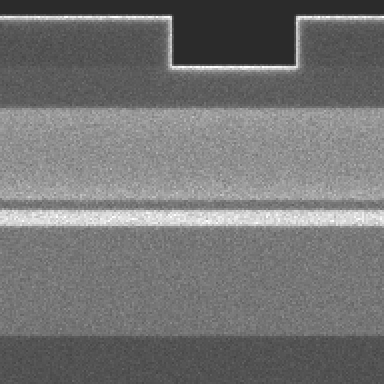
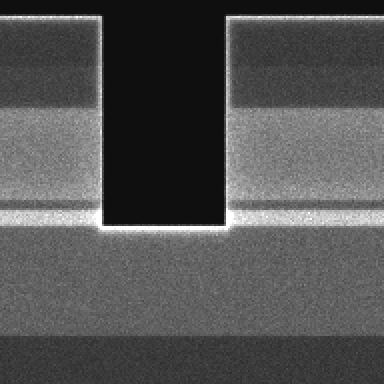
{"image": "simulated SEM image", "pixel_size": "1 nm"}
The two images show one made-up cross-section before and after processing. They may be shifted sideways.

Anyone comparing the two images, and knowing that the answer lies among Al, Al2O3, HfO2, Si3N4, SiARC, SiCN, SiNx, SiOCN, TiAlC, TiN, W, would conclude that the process removed HfO2 and Si3N4 and TiN and W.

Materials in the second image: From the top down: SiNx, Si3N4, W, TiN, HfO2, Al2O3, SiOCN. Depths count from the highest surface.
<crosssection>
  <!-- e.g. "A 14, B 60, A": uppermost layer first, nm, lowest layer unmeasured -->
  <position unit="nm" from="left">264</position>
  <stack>SiNx 50, Si3N4 42, W 92, TiN 10, HfO2 16, Al2O3 110, SiOCN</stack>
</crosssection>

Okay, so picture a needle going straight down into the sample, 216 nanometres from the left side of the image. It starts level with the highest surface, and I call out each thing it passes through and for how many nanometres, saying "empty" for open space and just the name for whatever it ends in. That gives empty 210, Al2O3 110, SiOCN